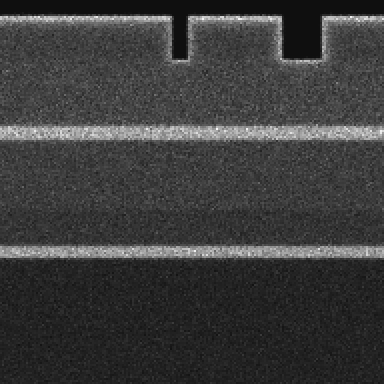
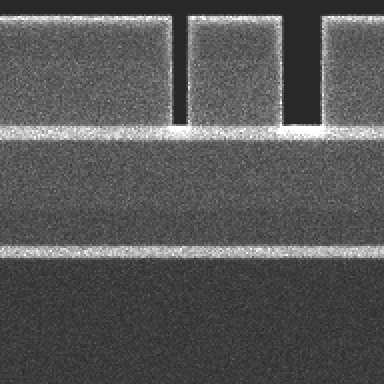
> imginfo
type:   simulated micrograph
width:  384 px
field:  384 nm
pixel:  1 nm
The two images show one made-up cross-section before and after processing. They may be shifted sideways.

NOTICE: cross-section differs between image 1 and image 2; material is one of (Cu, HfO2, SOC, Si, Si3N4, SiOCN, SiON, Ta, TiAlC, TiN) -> removed: TiN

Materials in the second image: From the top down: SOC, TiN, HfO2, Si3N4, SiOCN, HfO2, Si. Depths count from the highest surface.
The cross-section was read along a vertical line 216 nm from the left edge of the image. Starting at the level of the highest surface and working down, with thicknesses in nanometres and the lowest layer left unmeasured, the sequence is SOC 44, TiN 66, HfO2 14, Si3N4 70, SiOCN 36, HfO2 12, Si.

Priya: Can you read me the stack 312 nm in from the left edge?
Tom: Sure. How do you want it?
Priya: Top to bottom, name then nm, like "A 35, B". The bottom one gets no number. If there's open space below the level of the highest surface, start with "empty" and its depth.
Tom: empty 110, HfO2 14, Si3N4 70, SiOCN 36, HfO2 12, Si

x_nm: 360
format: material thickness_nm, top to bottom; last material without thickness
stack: SOC 44, TiN 66, HfO2 14, Si3N4 70, SiOCN 36, HfO2 12, Si